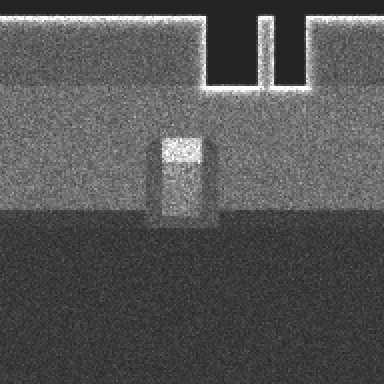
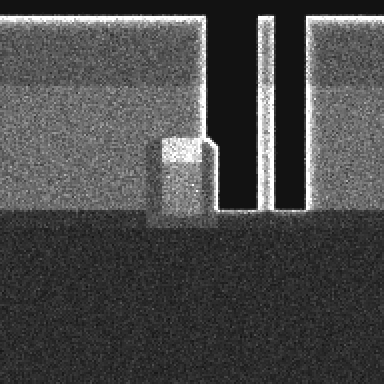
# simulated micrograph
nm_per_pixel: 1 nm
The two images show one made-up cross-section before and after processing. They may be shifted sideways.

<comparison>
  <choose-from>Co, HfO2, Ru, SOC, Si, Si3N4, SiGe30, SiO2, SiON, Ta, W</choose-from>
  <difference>SiO2 removed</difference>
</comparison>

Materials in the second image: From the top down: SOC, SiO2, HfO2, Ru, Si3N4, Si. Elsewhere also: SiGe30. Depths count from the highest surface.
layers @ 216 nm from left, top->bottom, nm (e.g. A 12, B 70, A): empty 130, Si3N4 82, Si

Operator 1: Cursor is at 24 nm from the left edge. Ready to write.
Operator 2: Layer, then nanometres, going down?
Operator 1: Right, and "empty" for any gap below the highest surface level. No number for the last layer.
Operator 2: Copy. SOC 70, SiO2 124, SiGe30 18, Si